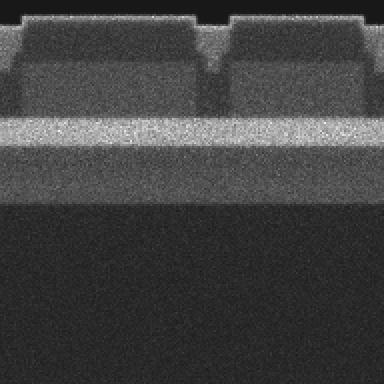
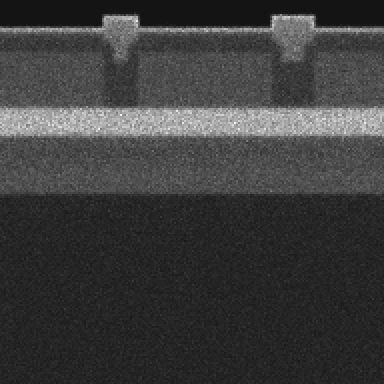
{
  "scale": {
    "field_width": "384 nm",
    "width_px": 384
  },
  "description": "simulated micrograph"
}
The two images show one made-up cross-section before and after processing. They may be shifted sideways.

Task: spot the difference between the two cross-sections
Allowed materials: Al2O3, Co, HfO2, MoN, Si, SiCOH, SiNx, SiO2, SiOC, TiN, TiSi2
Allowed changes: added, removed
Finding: removed SiNx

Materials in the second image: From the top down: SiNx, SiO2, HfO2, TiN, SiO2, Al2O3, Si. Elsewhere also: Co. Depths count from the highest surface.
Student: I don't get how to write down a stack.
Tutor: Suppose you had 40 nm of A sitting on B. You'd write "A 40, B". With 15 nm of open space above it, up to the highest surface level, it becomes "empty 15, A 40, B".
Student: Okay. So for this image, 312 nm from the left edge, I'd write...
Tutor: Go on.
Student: Co 26, SiNx 66, HfO2 28, TiN 22, SiO2 12, Al2O3 24, Si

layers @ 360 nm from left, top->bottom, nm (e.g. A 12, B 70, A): empty 12, SiNx 24, SiO2 56, HfO2 28, TiN 22, SiO2 12, Al2O3 24, Si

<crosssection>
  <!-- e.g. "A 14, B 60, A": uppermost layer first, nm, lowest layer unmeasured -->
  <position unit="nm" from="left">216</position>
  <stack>empty 12, SiNx 24, SiO2 56, HfO2 28, TiN 22, SiO2 12, Al2O3 24, Si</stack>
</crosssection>